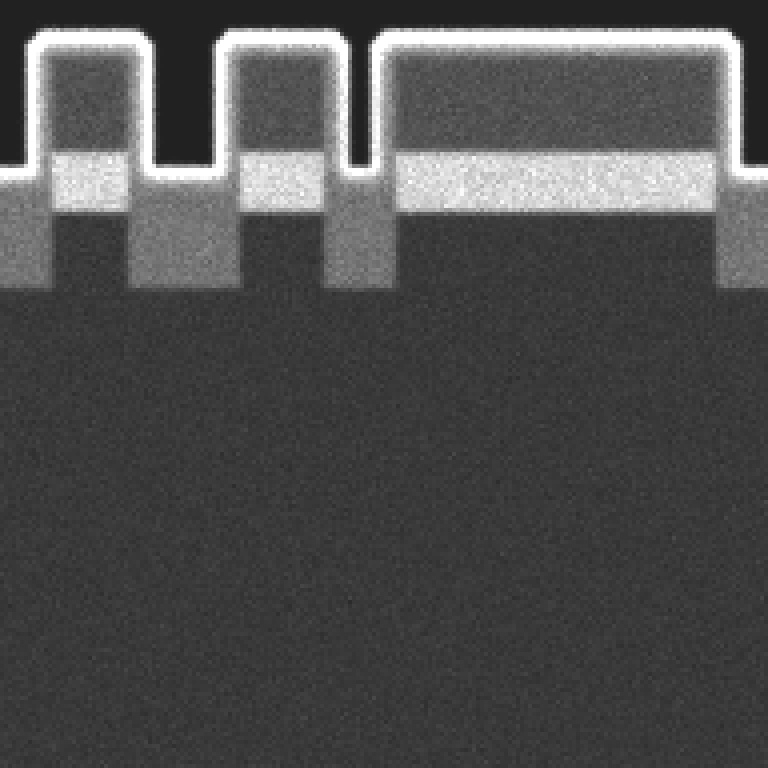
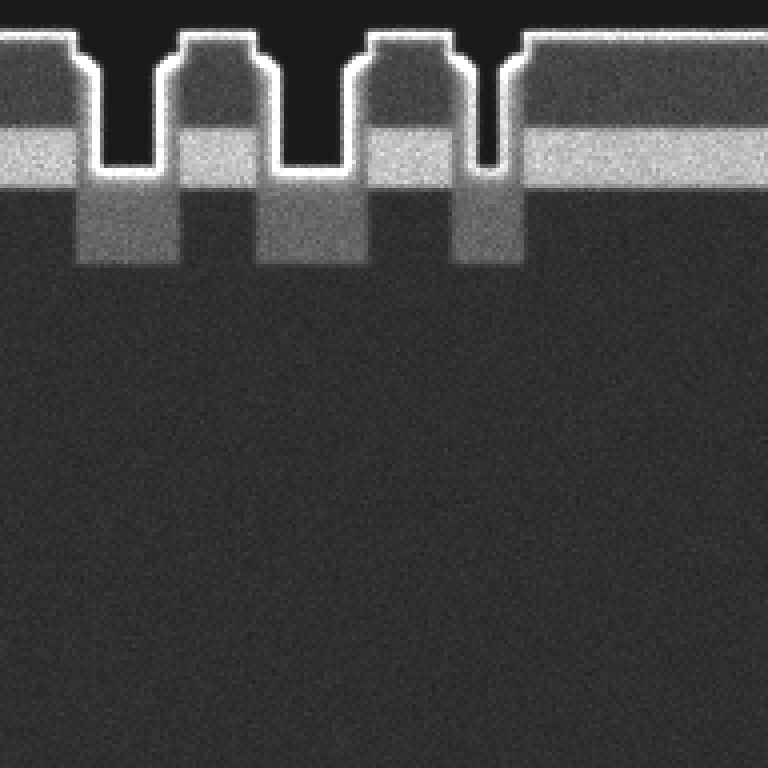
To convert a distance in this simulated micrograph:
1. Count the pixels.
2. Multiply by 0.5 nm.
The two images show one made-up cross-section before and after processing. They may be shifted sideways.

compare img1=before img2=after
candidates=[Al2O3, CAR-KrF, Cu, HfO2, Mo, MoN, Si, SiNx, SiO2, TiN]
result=removed:Al2O3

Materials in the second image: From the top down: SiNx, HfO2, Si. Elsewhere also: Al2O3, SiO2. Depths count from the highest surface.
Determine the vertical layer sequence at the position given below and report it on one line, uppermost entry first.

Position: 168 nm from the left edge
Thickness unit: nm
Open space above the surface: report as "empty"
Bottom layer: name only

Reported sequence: empty 68, SiO2 48, Si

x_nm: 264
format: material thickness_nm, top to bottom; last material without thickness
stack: SiNx 48, HfO2 30, Si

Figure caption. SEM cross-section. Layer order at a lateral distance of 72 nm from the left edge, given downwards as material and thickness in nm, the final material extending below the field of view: empty 68, SiO2 48, Si